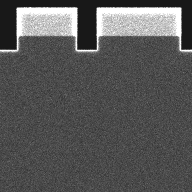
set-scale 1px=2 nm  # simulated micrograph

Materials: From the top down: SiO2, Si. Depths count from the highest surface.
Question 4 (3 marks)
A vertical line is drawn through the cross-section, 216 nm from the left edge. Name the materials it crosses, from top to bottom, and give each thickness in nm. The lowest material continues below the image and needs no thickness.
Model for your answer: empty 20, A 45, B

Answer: SiO2 56, Si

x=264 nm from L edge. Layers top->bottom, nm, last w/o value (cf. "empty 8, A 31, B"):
SiO2 56, Si